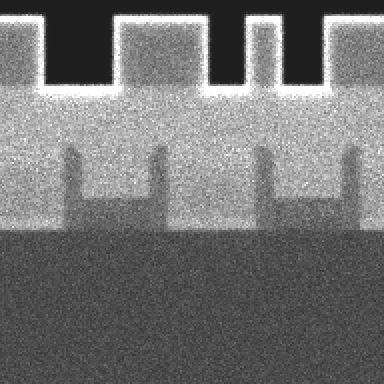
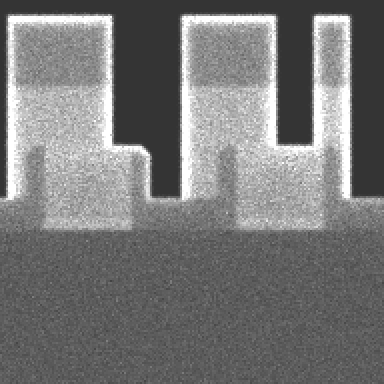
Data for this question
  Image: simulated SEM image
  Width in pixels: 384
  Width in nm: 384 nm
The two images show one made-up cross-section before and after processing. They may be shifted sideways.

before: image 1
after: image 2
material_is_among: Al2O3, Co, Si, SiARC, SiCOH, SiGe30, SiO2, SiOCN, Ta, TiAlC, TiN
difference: SiO2, removed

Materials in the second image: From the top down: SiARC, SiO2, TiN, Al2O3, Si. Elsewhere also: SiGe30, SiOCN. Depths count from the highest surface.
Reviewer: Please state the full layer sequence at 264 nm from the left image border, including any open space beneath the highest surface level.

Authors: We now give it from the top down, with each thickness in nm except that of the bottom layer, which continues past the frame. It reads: SiARC 70, SiO2 60, TiN 72, Al2O3 12, Si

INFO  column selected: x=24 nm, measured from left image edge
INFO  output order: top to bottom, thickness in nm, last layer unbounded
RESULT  SiARC 70, SiO2 112, SiGe30 32, Si